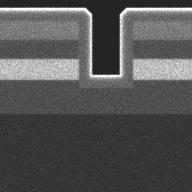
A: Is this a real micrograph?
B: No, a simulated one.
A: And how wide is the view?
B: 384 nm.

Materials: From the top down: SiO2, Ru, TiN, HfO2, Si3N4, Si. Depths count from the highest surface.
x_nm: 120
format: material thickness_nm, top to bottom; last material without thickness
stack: SiO2 26, Ru 38, TiN 38, HfO2 42, Si3N4 68, Si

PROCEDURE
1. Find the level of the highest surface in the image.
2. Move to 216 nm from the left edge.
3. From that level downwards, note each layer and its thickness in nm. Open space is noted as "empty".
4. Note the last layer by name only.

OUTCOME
empty 134, SiO2 26, Si3N4 52, Si